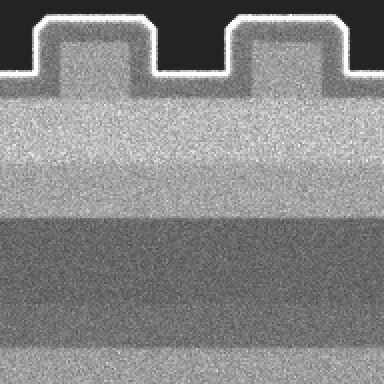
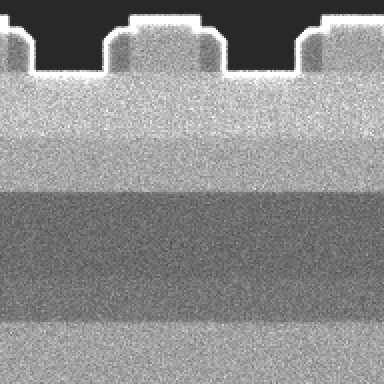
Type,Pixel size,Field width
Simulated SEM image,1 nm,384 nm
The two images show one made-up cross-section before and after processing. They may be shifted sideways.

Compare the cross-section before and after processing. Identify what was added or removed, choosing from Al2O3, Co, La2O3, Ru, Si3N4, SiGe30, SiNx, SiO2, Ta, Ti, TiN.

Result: Si3N4 removed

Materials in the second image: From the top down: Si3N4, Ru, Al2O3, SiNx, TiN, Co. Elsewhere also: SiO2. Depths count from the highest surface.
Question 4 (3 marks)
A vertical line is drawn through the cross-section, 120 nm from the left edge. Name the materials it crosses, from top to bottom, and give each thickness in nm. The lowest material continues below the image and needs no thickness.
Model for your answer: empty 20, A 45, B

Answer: empty 12, Si3N4 44, Ru 66, Al2O3 54, SiNx 86, TiN 44, Co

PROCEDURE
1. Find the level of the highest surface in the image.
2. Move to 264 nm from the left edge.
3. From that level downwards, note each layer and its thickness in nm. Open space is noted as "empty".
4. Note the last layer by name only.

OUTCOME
empty 56, Ru 66, Al2O3 54, SiNx 86, TiN 44, Co